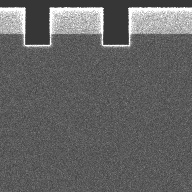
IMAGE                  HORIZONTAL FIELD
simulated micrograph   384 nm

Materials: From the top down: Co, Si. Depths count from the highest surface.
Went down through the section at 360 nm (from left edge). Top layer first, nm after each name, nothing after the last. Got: Co 52, Si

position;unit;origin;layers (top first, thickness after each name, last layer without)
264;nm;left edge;Co 52, Si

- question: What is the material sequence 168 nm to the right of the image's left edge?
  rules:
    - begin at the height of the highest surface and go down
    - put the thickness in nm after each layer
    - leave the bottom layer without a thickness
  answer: Co 52, Si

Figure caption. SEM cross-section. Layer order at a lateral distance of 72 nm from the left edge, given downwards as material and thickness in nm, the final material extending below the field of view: empty 74, Si